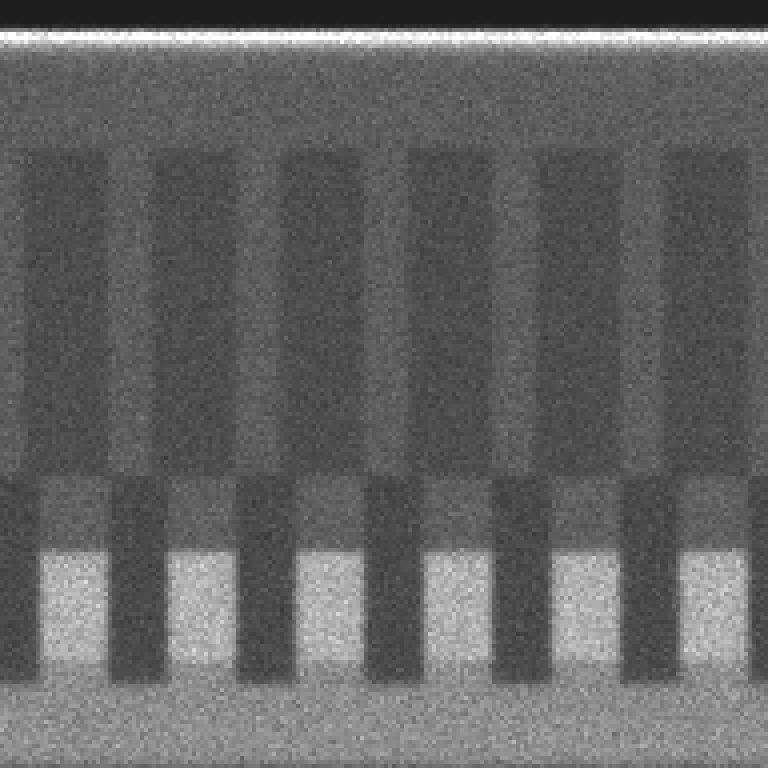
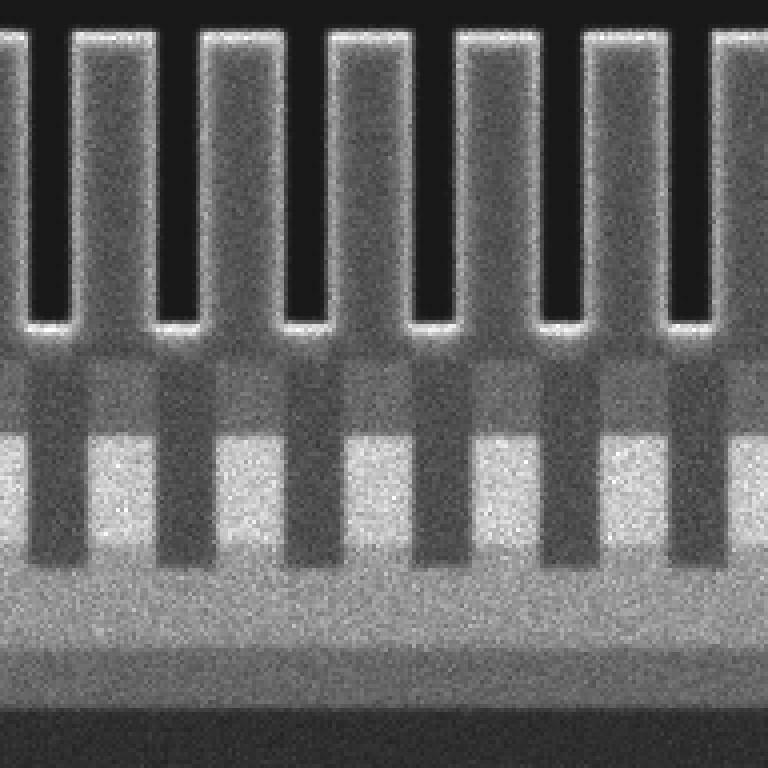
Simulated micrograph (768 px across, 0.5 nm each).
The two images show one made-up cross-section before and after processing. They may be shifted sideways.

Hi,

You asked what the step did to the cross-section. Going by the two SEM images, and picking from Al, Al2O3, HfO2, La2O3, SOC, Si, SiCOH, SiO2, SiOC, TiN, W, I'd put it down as SiO2, removed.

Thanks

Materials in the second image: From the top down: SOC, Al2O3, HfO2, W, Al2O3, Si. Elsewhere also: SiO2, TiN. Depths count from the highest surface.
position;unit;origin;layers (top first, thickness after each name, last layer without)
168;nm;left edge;SOC 164, TiN 104, W 40, Al2O3 30, Si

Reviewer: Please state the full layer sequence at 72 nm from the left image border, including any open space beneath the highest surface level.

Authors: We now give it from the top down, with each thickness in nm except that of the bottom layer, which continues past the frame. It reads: SOC 164, Al2O3 38, HfO2 54, W 52, Al2O3 30, Si